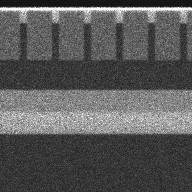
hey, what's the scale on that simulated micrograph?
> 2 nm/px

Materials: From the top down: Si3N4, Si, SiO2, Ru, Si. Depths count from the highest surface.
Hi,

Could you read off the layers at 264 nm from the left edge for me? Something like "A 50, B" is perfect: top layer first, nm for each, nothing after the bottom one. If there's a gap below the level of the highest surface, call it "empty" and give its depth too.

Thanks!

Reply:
Si3N4 104, Si 60, SiO2 44, Ru 44, Si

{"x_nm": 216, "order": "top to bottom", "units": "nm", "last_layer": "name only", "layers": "Si3N4 104, Si 60, SiO2 44, Ru 44, Si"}